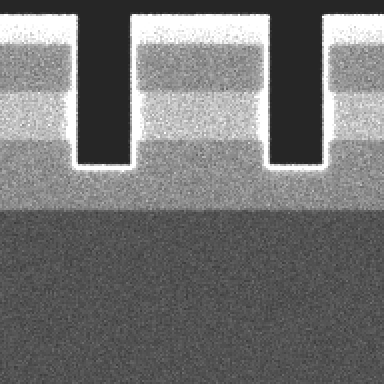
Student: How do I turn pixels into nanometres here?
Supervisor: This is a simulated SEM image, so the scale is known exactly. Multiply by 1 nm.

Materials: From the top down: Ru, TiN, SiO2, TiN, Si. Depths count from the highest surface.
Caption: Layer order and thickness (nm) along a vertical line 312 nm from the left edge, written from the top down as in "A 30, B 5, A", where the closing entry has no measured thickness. empty 150, TiN 44, Si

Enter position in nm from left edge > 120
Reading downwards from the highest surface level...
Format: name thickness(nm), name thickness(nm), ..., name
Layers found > empty 150, TiN 44, Si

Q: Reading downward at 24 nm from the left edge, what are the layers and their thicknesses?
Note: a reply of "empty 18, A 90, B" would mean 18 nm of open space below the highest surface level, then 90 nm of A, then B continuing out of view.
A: Ru 28, TiN 48, SiO2 48, TiN 70, Si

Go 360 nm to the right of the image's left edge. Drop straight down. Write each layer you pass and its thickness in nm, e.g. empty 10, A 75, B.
Ru 28, TiN 48, SiO2 48, TiN 70, Si